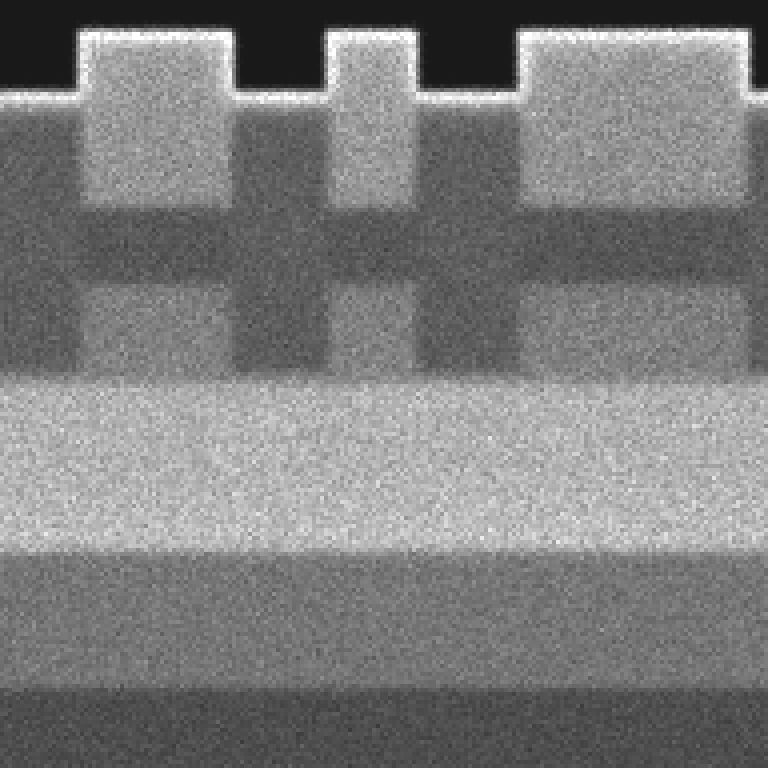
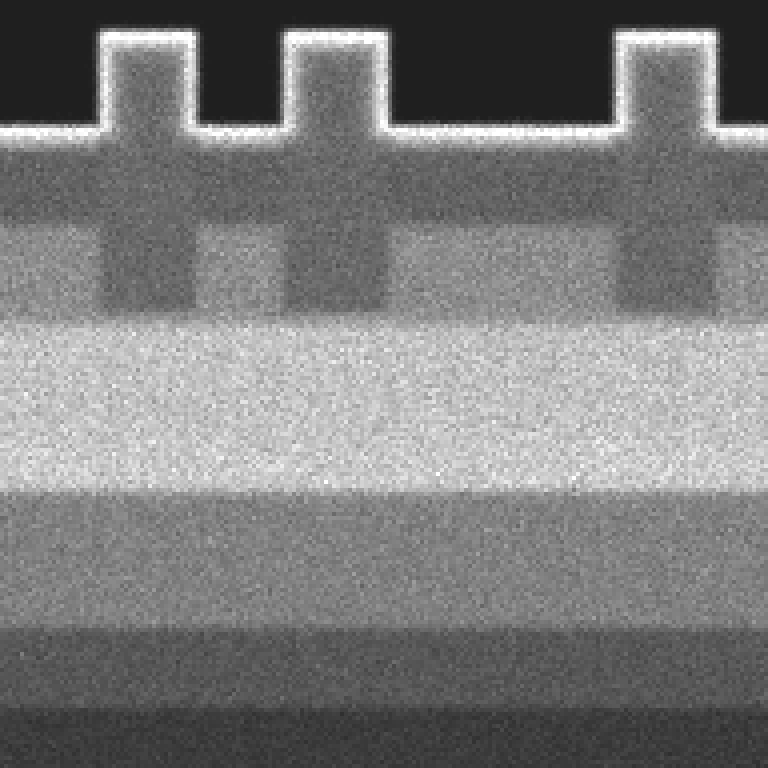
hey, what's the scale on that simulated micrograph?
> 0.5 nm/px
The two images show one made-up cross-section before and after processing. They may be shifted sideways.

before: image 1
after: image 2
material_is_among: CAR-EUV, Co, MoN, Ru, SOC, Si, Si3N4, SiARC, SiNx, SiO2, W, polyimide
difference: Ru, removed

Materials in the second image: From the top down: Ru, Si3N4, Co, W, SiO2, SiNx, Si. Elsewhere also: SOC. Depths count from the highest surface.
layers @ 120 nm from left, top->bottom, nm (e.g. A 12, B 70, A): empty 48, Ru 10, Si3N4 38, Co 50, W 84, SiO2 68, SiNx 40, Si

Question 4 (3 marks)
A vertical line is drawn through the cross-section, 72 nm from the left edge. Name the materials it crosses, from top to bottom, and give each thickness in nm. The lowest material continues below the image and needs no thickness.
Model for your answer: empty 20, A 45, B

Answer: SOC 140, Co 6, W 84, SiO2 68, SiNx 40, Si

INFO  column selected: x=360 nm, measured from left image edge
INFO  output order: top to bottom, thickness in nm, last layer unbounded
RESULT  empty 48, Ru 10, Si3N4 38, Co 50, W 84, SiO2 68, SiNx 40, Si